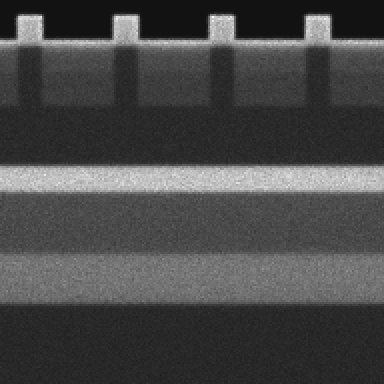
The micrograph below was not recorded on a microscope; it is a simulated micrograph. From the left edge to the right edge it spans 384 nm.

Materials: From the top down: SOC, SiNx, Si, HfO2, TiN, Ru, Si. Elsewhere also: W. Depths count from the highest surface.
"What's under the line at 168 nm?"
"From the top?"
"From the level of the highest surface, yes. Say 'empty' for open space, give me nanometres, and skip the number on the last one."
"empty 24, SOC 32, SiNx 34, Si 60, HfO2 26, TiN 62, Ru 50, Si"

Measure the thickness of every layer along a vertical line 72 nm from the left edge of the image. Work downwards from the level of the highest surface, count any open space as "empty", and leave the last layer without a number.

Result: empty 24, SOC 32, SiNx 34, Si 60, HfO2 26, TiN 62, Ru 50, Si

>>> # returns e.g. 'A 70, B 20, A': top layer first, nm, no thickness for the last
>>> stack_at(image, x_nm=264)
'empty 24, SOC 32, SiNx 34, Si 60, HfO2 26, TiN 62, Ru 50, Si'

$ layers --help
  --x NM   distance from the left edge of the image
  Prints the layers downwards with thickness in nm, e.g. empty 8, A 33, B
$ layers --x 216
W 30, Si 120, HfO2 26, TiN 62, Ru 50, Si